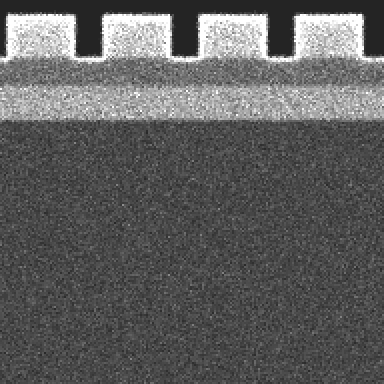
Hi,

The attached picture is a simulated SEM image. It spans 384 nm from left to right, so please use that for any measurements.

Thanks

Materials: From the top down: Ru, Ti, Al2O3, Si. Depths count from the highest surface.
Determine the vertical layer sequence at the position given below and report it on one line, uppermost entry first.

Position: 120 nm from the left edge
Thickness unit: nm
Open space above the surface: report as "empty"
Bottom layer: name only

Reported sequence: Ru 42, Ti 28, Al2O3 34, Si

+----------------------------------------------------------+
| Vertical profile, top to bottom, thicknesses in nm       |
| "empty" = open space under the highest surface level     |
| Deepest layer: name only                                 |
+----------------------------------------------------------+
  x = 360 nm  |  Ru 42, Ti 28, Al2O3 34, Si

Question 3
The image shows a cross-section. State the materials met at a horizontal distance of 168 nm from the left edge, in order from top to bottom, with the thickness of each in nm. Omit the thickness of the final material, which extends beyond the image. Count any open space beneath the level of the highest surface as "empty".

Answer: Ru 42, Ti 28, Al2O3 34, Si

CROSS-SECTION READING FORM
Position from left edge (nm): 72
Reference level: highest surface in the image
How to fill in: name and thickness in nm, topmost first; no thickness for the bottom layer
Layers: Ru 42, Ti 28, Al2O3 34, Si